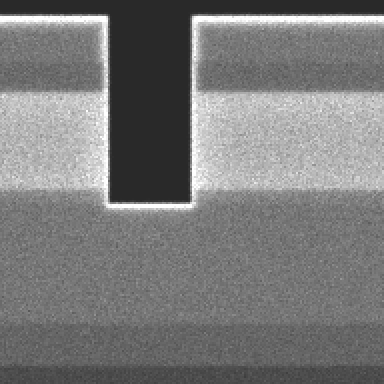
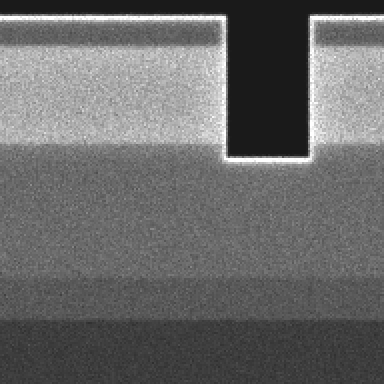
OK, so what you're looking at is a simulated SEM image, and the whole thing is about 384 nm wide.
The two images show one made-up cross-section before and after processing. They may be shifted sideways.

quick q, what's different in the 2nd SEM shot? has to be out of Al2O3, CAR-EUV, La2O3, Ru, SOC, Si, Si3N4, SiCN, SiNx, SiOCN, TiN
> SOC removed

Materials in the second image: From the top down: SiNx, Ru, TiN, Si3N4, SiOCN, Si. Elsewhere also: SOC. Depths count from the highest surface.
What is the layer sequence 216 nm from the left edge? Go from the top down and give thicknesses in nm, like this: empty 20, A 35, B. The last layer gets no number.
SiNx 30, Ru 98, TiN 14, Si3N4 120, SiOCN 42, Si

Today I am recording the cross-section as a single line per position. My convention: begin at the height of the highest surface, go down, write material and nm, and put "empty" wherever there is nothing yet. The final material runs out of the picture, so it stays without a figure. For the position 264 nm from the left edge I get empty 142, Si3N4 120, SiOCN 42, Si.